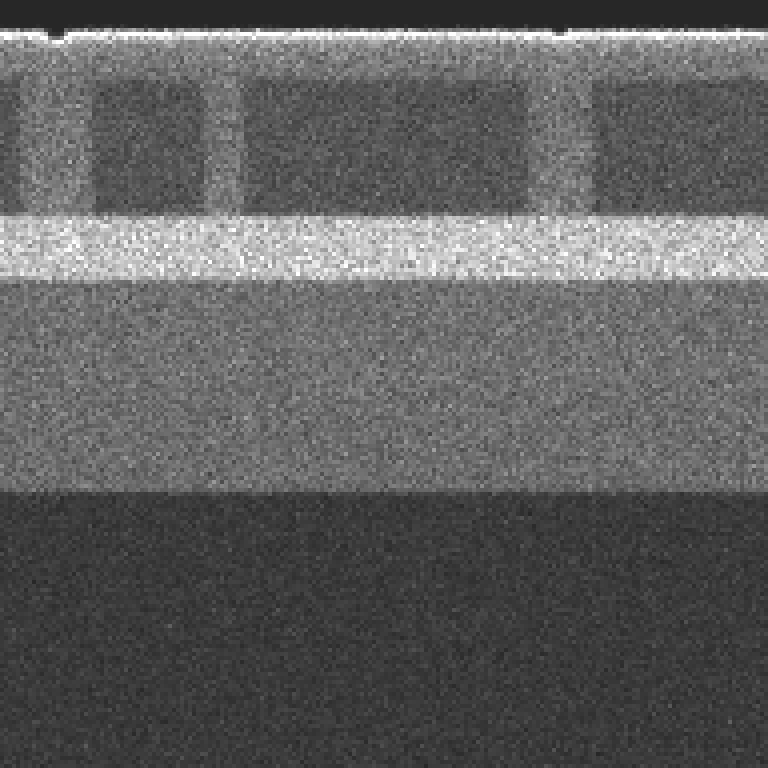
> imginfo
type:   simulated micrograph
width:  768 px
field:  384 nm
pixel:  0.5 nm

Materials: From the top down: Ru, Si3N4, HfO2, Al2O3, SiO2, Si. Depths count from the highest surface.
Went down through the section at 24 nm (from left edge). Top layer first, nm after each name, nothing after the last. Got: empty 4, Ru 88, HfO2 32, Al2O3 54, SiO2 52, Si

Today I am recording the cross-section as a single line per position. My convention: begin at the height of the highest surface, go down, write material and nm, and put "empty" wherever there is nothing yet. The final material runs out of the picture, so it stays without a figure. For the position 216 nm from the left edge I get Ru 24, Si3N4 68, HfO2 32, Al2O3 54, SiO2 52, Si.